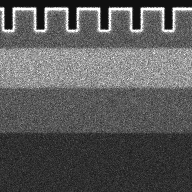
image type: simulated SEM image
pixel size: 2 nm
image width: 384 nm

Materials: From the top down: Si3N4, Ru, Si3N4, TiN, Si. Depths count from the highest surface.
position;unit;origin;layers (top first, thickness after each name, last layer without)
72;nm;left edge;empty 44, Si3N4 36, Ru 80, Si3N4 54, TiN 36, Si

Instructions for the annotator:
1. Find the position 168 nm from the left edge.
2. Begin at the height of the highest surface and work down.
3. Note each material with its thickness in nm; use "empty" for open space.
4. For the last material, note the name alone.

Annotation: Si3N4 80, Ru 80, Si3N4 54, TiN 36, Si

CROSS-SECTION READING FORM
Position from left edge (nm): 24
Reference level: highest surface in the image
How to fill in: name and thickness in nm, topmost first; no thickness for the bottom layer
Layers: empty 44, Si3N4 36, Ru 80, Si3N4 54, TiN 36, Si